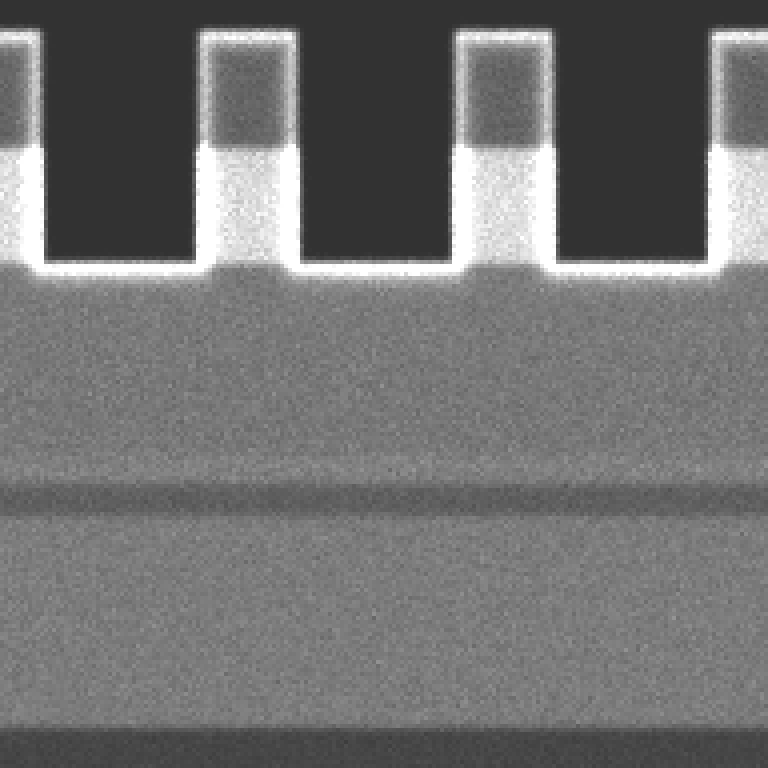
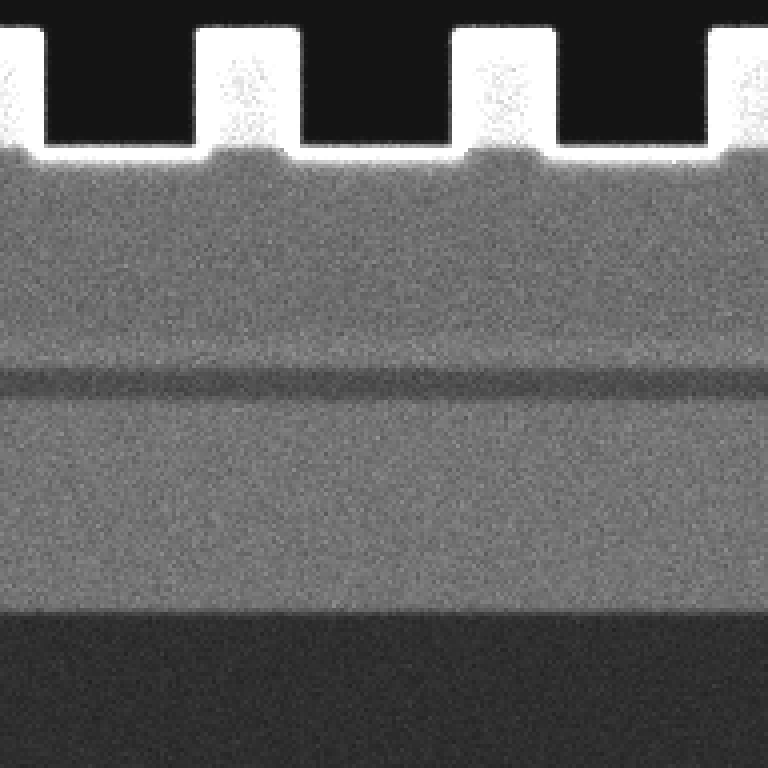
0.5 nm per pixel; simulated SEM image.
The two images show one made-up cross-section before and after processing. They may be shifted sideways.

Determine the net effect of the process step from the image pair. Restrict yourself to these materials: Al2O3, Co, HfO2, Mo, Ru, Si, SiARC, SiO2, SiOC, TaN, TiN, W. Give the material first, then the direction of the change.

SiARC: removed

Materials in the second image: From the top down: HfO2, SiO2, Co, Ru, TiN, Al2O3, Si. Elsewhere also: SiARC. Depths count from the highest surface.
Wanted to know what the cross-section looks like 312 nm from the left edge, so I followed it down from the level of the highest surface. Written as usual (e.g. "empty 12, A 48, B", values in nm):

empty 58, SiO2 44, Co 52, Ru 14, TiN 16, Al2O3 106, Si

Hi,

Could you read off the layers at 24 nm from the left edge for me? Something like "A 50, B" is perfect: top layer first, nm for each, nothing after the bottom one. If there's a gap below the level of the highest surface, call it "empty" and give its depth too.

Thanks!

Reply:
empty 58, SiO2 44, Co 52, Ru 14, TiN 16, Al2O3 106, Si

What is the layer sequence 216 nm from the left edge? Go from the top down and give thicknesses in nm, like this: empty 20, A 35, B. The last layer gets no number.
empty 58, SiO2 44, Co 52, Ru 14, TiN 16, Al2O3 106, Si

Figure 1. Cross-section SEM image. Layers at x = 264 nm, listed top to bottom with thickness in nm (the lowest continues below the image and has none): HfO2 58, SiO2 44, Co 52, Ru 14, TiN 16, Al2O3 106, Si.